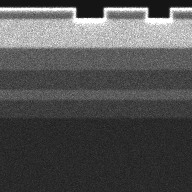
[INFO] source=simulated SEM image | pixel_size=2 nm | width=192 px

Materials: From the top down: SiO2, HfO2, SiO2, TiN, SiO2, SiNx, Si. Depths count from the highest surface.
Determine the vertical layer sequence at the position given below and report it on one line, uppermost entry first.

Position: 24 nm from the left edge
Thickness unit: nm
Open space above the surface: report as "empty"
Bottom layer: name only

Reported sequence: SiO2 22, HfO2 58, SiO2 44, TiN 40, SiO2 20, SiNx 36, Si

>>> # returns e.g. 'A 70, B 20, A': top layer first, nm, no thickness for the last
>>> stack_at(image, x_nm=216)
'SiO2 22, HfO2 58, SiO2 44, TiN 40, SiO2 20, SiNx 36, Si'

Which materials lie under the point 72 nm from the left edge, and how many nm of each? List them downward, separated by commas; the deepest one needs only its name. SiO2 22, HfO2 58, SiO2 44, TiN 40, SiO2 20, SiNx 36, Si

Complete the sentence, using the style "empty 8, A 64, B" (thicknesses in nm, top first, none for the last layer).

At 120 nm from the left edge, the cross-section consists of SiO2 22, HfO2 58, SiO2 44, TiN 40, SiO2 20, SiNx 36, Si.